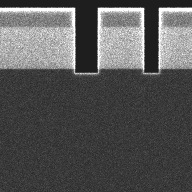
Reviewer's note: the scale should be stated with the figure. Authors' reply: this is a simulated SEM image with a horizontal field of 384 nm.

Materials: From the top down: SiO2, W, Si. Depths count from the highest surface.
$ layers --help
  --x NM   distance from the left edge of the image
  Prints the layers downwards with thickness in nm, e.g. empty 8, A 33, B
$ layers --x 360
SiO2 38, W 84, Si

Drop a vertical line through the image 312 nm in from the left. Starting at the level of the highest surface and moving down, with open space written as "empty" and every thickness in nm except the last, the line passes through empty 130, Si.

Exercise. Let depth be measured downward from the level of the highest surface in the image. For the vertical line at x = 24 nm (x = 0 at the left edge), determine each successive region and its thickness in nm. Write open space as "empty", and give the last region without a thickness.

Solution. SiO2 38, W 84, Si